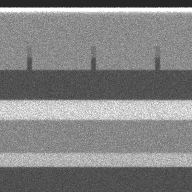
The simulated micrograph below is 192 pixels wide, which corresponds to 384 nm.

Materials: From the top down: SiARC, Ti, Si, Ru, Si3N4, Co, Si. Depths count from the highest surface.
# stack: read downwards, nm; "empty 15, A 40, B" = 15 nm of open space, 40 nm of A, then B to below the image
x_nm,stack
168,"SiARC 124, Si 60, Ru 40, Si3N4 66, Co 28, Si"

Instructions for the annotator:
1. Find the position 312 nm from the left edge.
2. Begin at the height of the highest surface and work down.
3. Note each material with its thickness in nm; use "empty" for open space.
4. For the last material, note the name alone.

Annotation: SiARC 76, Ti 24, Si 84, Ru 40, Si3N4 66, Co 28, Si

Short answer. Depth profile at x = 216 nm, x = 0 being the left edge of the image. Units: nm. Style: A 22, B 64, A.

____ SiARC 124, Si 60, Ru 40, Si3N4 66, Co 28, Si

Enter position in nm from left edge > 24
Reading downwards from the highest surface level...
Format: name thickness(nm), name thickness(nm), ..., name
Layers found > SiARC 124, Si 60, Ru 40, Si3N4 66, Co 28, Si